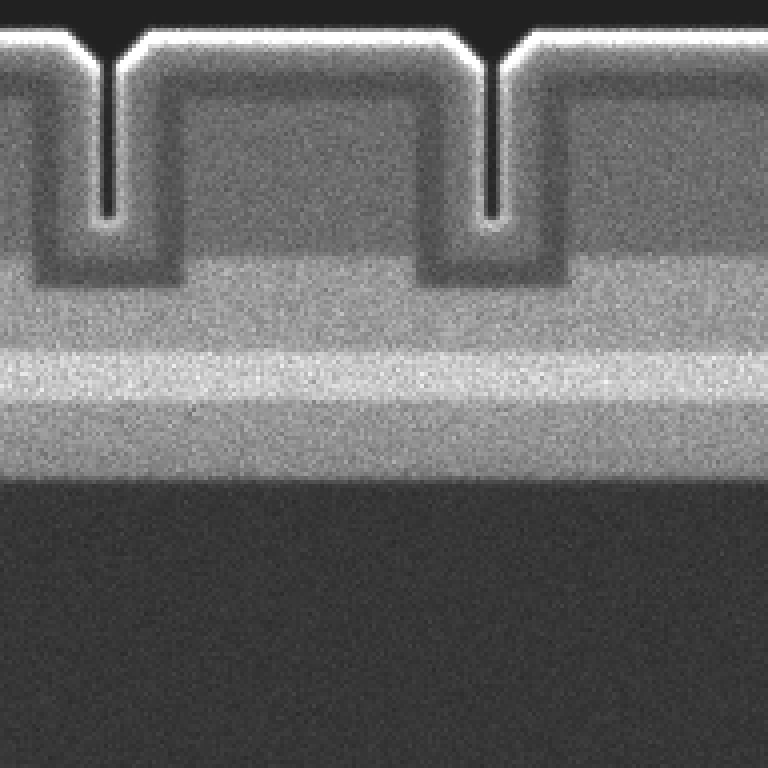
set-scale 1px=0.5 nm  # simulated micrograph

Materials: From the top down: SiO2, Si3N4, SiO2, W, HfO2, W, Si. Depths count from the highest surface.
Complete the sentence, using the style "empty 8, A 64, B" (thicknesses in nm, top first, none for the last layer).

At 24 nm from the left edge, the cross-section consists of SiO2 22, Si3N4 106, W 32, HfO2 24, W 40, Si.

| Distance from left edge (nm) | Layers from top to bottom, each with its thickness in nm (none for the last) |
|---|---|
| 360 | SiO2 20, Si3N4 14, SiO2 78, W 48, HfO2 24, W 40, Si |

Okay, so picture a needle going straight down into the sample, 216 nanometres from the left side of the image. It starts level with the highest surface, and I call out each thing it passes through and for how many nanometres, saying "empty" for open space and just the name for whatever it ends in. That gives SiO2 22, Si3N4 106, W 32, HfO2 24, W 40, Si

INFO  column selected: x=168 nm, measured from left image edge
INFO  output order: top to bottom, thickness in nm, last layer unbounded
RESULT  SiO2 20, Si3N4 14, SiO2 78, W 48, HfO2 24, W 40, Si